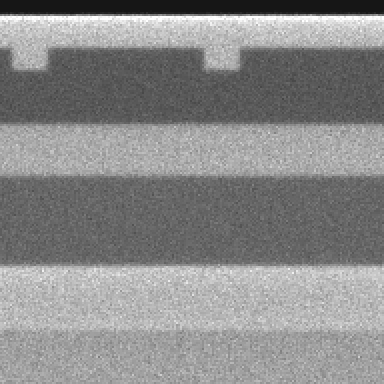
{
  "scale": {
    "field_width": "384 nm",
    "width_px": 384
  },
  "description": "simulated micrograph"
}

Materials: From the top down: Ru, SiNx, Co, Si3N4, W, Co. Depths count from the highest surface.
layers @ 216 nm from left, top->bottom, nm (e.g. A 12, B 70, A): Ru 54, SiNx 54, Co 52, Si3N4 90, W 64, Co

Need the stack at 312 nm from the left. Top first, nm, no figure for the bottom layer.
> Ru 32, SiNx 76, Co 52, Si3N4 90, W 64, Co